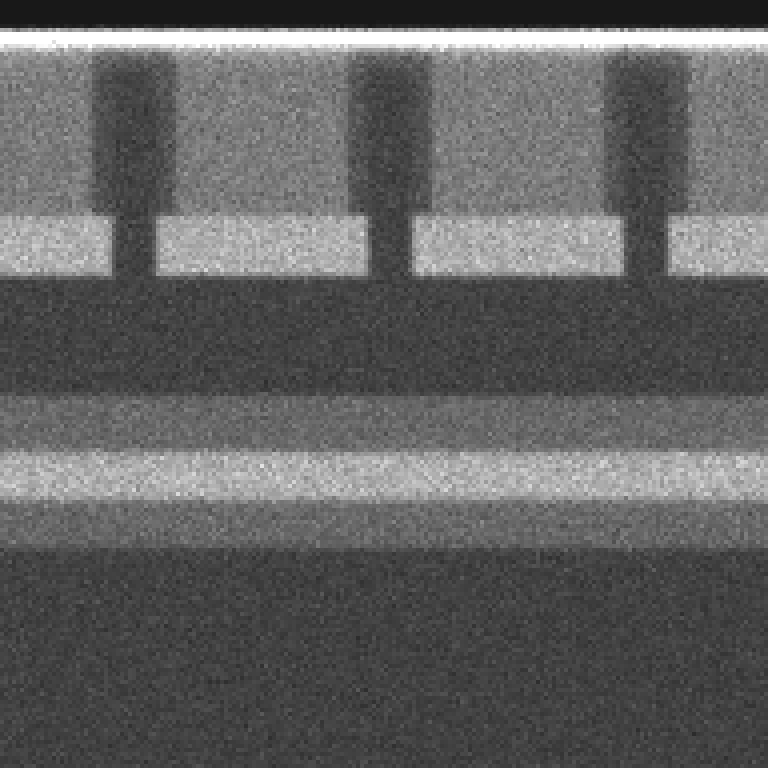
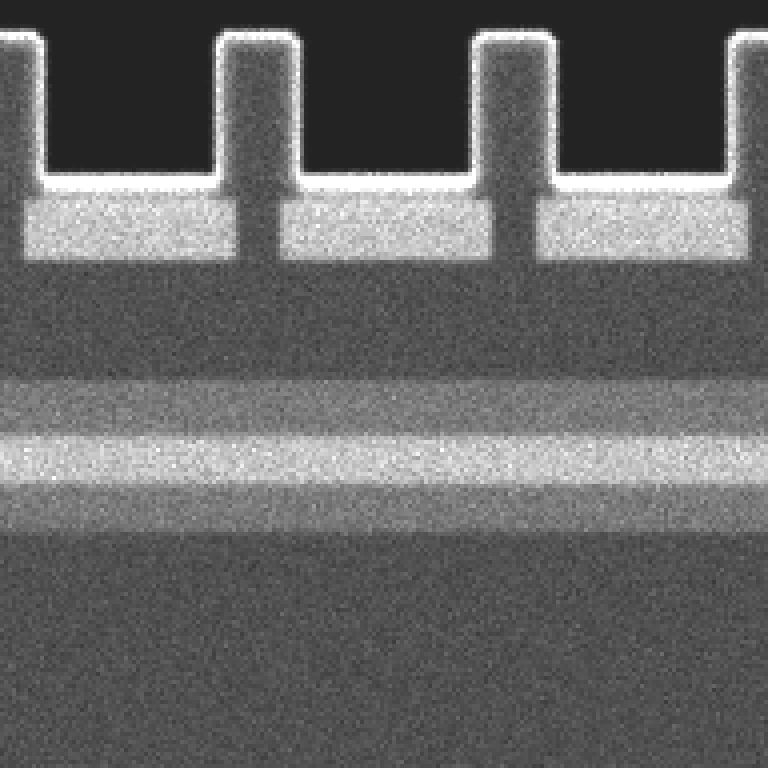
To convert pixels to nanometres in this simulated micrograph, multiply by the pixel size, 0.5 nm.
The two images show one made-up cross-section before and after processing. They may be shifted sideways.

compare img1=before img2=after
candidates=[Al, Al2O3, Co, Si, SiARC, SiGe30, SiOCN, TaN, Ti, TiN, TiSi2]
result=removed:SiARC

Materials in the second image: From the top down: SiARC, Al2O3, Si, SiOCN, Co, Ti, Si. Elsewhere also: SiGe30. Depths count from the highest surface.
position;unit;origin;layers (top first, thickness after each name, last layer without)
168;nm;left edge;empty 72, SiARC 12, Al2O3 30, Si 60, SiOCN 28, Co 24, Ti 24, Si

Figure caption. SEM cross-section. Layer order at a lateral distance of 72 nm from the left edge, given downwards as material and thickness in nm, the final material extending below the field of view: empty 72, SiARC 12, Al2O3 30, Si 60, SiOCN 28, Co 24, Ti 24, Si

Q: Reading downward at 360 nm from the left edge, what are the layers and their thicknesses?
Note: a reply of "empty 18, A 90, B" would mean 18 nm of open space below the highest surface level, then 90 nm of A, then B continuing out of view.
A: empty 72, SiARC 12, Al2O3 30, Si 60, SiOCN 28, Co 24, Ti 24, Si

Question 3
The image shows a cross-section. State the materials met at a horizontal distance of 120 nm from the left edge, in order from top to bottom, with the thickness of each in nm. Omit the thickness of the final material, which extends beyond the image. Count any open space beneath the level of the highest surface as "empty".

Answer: SiGe30 10, Si 164, SiOCN 28, Co 24, Ti 24, Si